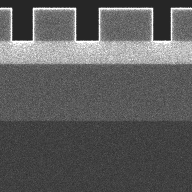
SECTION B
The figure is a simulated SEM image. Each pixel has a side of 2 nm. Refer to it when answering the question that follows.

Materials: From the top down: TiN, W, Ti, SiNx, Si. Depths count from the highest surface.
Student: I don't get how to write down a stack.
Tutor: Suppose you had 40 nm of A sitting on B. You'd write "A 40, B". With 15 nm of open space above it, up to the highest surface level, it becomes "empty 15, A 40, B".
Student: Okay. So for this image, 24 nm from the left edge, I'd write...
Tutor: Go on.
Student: empty 66, W 46, Ti 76, SiNx 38, Si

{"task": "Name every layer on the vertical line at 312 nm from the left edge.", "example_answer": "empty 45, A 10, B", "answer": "empty 66, W 46, Ti 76, SiNx 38, Si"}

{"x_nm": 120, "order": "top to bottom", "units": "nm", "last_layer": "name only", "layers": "TiN 66, W 46, Ti 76, SiNx 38, Si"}